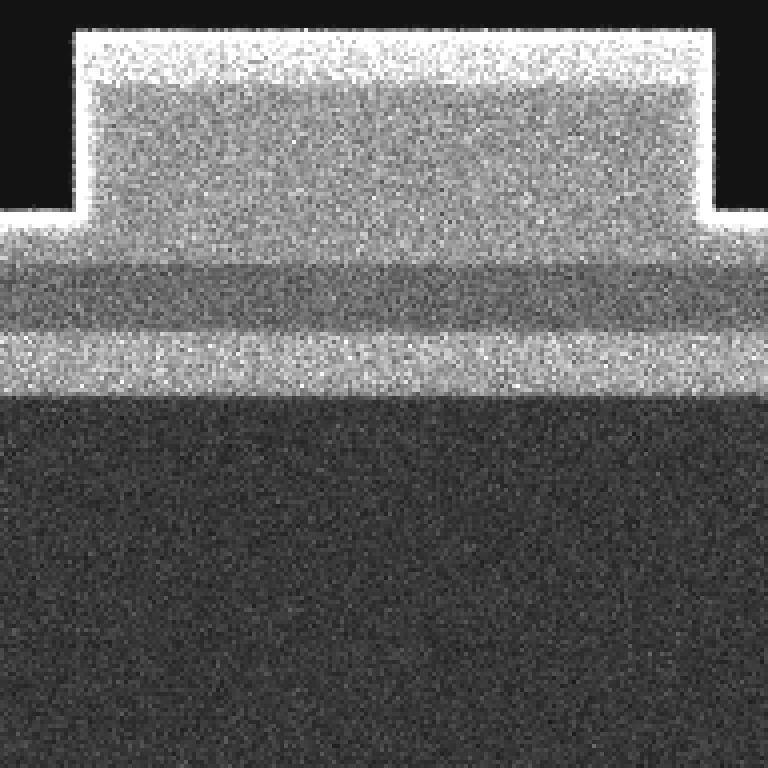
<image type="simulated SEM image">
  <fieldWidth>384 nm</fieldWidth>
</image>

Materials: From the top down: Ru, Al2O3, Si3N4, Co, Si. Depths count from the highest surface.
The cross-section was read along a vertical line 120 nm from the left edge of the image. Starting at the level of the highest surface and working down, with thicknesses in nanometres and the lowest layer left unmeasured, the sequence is Ru 26, Al2O3 90, Si3N4 34, Co 32, Si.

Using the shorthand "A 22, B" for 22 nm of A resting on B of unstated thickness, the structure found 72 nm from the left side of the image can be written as Ru 26, Al2O3 90, Si3N4 34, Co 32, Si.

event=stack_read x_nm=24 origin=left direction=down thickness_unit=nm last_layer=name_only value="empty 90, Al2O3 26, Si3N4 34, Co 32, Si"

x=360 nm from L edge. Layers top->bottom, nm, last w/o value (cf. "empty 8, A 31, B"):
empty 90, Al2O3 26, Si3N4 34, Co 32, Si